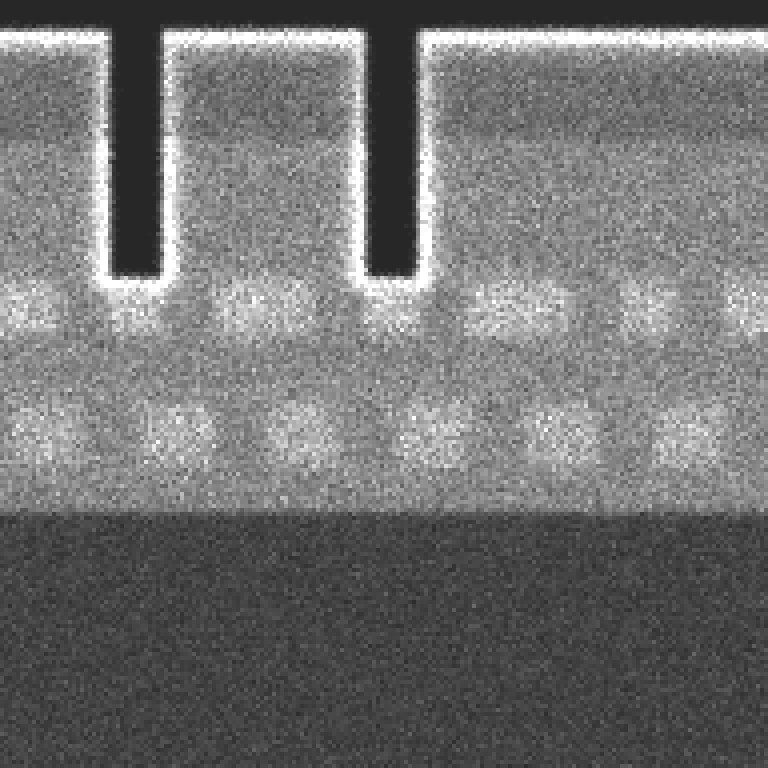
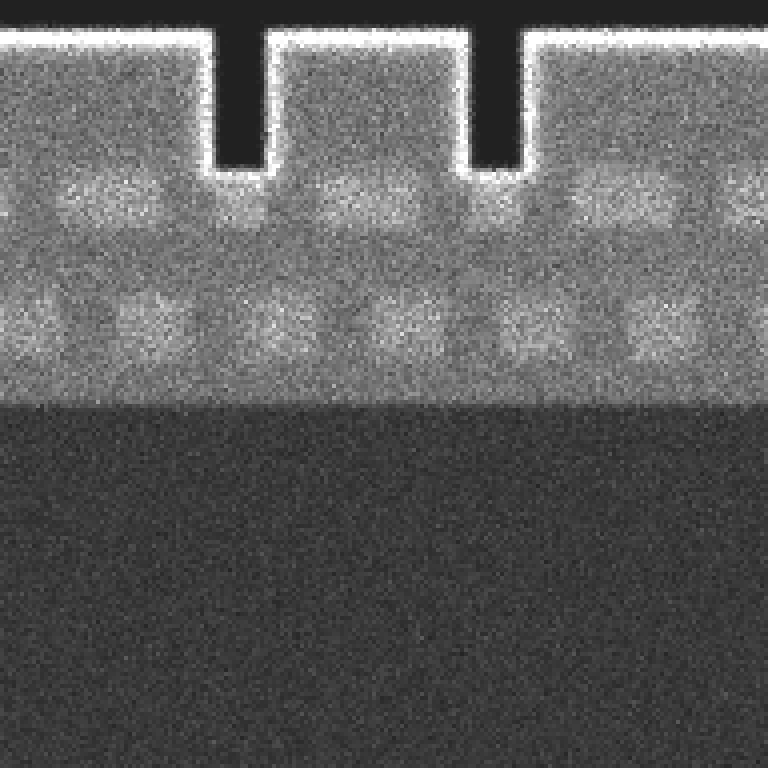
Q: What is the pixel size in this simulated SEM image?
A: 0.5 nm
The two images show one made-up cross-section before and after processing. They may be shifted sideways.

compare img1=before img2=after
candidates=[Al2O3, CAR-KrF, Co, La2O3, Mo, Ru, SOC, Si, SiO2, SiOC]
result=removed:SOC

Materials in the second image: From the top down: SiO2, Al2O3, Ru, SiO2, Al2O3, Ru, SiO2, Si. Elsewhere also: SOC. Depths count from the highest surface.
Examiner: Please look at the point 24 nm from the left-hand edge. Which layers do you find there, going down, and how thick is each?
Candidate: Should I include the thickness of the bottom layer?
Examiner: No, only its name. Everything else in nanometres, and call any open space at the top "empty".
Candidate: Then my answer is SiO2 62, Al2O3 8, SiO2 50, Al2O3 12, Ru 32, SiO2 22, Si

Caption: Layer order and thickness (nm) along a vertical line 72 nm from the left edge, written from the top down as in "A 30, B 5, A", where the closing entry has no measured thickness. SiO2 62, Al2O3 8, Ru 28, SiO2 22, Al2O3 12, Ru 32, SiO2 22, Si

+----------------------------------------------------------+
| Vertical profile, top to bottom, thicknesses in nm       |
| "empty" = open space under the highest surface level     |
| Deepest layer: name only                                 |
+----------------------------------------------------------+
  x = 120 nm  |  empty 70, Ru 28, SiO2 22, Al2O3 12, SiO2 54, Si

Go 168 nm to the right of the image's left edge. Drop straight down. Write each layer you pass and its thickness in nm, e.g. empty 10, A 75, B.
SiO2 62, Al2O3 8, Ru 28, SiO2 22, Al2O3 12, SiO2 54, Si